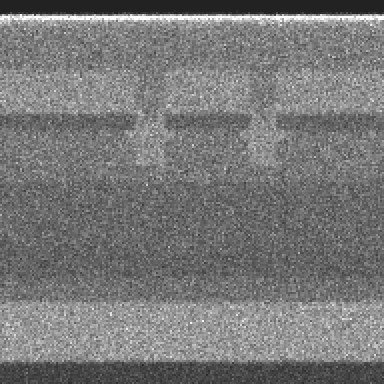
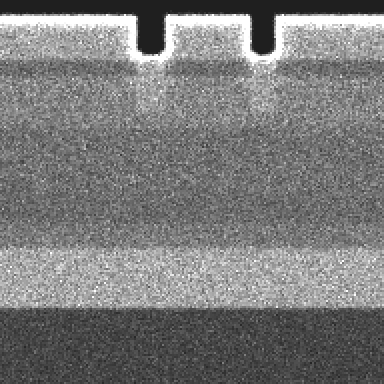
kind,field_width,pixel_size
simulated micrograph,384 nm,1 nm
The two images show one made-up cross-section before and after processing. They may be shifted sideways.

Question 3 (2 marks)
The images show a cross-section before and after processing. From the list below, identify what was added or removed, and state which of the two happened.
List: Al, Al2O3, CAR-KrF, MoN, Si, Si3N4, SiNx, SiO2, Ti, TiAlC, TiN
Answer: TiN was removed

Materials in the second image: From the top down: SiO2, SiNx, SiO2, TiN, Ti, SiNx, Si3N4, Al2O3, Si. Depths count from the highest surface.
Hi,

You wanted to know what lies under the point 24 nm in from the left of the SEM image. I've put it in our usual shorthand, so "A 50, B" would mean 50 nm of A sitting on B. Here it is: SiO2 44, SiNx 16, TiN 52, Ti 66, SiNx 30, Si3N4 24, Al2O3 60, Si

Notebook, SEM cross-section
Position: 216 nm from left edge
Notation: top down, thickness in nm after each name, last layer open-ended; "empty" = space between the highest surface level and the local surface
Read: SiO2 44, SiNx 16, TiN 52, Ti 66, SiNx 30, Si3N4 24, Al2O3 60, Si